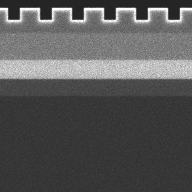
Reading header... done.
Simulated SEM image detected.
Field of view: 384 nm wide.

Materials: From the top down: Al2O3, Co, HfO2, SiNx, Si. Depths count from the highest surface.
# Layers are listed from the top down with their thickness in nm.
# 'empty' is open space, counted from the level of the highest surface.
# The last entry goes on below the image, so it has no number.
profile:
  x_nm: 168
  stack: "Al2O3 50, Co 54, HfO2 38, SiNx 34, Si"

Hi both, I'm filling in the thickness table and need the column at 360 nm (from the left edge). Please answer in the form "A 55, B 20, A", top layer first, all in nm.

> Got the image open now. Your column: Al2O3 50, Co 54, HfO2 38, SiNx 34, Si